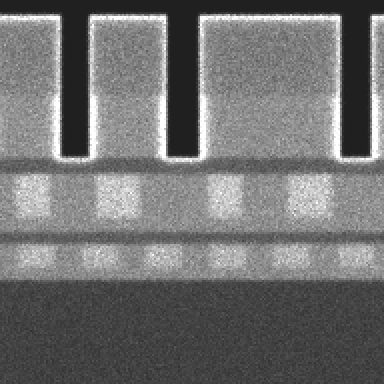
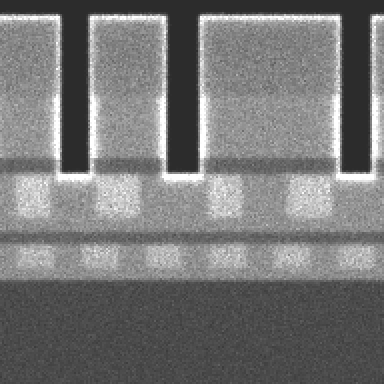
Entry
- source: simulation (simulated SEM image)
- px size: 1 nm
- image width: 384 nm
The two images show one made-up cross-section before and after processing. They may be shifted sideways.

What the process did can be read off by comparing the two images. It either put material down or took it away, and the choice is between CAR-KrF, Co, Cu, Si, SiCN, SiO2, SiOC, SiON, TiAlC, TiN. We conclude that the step removed SiCN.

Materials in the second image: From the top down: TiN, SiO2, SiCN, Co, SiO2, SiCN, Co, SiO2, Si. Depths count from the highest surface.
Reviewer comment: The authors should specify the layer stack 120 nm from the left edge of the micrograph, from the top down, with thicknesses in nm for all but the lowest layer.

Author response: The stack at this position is TiN 80, SiO2 62, SiCN 16, Co 44, SiO2 14, SiCN 12, SiO2 36, Si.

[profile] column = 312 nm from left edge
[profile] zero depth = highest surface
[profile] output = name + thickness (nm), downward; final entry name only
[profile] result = TiN 80, SiO2 62, SiCN 16, Co 44, SiO2 14, SiCN 12, SiO2 36, Si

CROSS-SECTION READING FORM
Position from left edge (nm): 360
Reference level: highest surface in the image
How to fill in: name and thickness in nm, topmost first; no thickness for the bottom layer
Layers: empty 158, SiO2 58, SiCN 12, Co 24, SiO2 12, Si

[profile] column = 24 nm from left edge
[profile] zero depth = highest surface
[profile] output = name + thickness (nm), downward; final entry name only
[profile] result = TiN 80, SiO2 62, SiCN 16, Co 44, SiO2 14, SiCN 12, Co 24, SiO2 12, Si